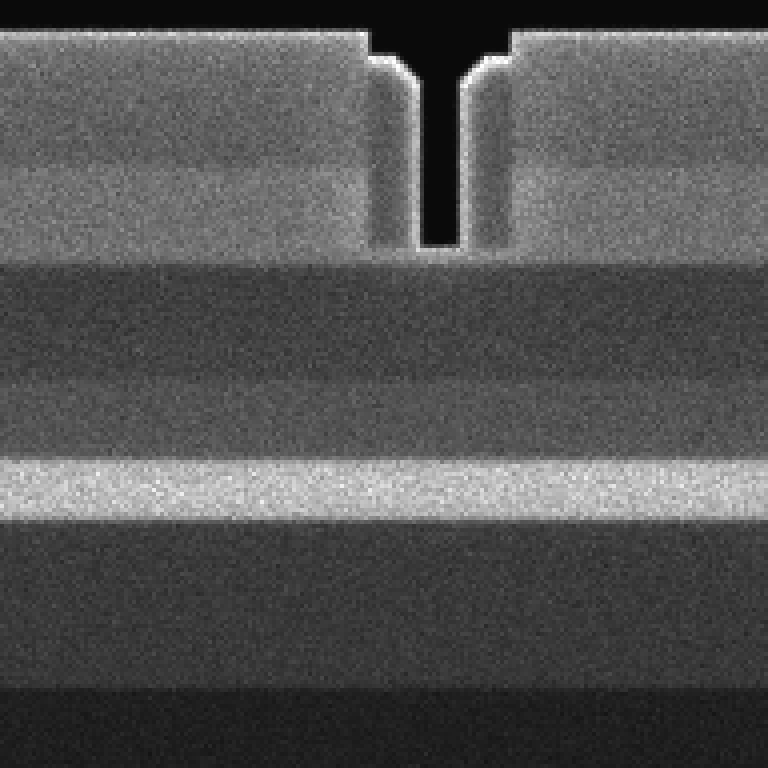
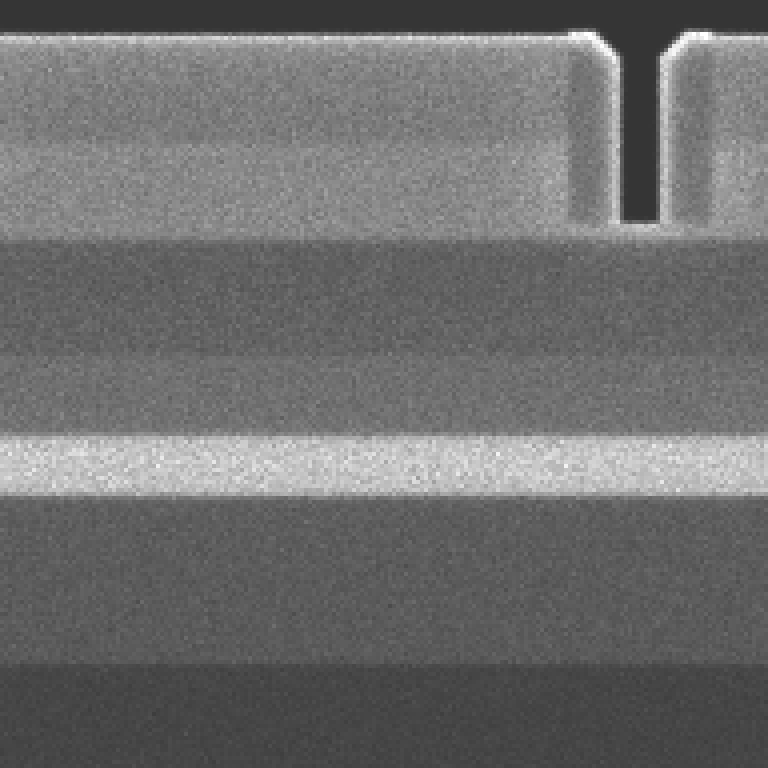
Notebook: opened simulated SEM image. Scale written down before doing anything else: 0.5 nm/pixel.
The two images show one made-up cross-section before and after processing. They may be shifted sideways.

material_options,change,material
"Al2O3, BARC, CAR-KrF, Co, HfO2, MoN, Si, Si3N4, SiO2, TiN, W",removed,Co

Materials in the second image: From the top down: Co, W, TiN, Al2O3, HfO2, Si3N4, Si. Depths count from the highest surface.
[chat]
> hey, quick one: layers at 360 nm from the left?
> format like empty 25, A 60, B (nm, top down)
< empty 2, Co 54, W 48, TiN 58, Al2O3 40, HfO2 30, Si3N4 84, Si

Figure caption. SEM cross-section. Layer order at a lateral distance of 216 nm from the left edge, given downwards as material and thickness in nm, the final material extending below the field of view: empty 2, Co 54, W 48, TiN 58, Al2O3 40, HfO2 30, Si3N4 84, Si